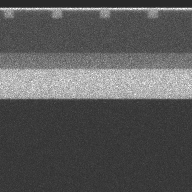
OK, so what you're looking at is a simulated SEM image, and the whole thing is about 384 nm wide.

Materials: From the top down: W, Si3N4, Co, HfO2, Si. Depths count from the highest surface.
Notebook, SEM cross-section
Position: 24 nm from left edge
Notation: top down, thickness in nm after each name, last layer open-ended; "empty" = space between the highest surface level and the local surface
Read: W 20, Si3N4 70, Co 32, HfO2 60, Si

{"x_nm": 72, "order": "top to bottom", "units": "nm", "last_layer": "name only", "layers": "Si3N4 90, Co 32, HfO2 60, Si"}